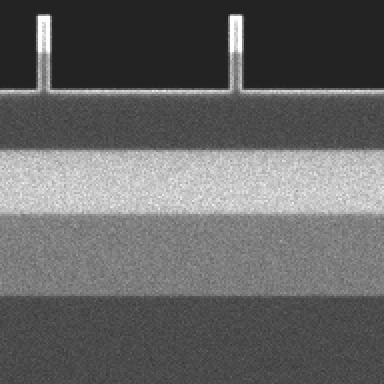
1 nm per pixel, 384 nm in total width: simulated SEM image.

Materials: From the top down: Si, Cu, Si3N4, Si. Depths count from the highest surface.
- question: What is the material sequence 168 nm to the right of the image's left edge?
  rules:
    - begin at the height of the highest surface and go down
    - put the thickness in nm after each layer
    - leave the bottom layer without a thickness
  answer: empty 74, Si 60, Cu 64, Si3N4 82, Si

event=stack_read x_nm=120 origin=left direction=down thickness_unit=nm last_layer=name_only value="empty 74, Si 60, Cu 64, Si3N4 82, Si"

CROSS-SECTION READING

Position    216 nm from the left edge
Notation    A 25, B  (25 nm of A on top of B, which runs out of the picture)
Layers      empty 74, Si 60, Cu 64, Si3N4 82, Si